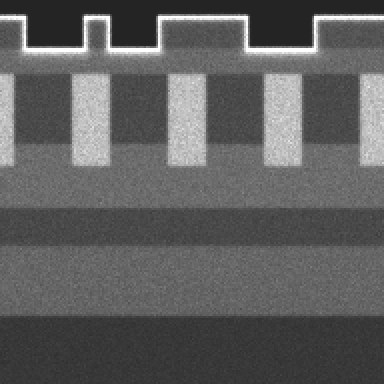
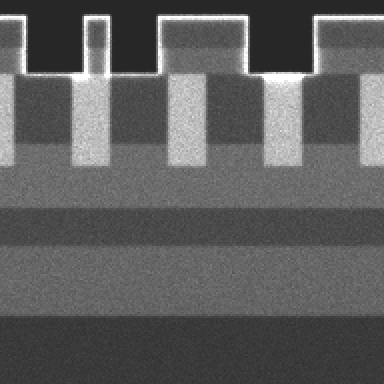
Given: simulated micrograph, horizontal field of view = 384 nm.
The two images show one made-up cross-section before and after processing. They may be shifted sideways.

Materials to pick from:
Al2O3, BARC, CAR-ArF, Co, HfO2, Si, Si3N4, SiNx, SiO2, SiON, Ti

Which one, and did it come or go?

SiO2 - removed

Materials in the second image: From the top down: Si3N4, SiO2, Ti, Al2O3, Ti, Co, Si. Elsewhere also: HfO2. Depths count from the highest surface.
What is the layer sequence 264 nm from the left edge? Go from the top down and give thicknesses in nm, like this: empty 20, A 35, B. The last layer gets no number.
empty 58, HfO2 92, Al2O3 42, Ti 38, Co 70, Si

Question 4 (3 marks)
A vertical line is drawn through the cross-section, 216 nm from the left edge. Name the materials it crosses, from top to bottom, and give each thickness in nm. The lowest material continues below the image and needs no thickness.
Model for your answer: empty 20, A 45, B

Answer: Si3N4 32, SiO2 26, Ti 70, Al2O3 64, Ti 38, Co 70, Si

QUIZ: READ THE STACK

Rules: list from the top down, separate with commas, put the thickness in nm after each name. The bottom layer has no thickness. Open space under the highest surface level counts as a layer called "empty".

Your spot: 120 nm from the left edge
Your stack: empty 58, Ti 70, Al2O3 64, Ti 38, Co 70, Si